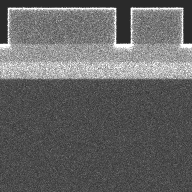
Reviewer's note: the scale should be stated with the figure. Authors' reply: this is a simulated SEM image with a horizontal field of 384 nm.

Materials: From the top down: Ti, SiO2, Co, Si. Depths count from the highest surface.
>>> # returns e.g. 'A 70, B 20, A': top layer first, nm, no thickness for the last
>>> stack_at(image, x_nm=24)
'Ti 72, SiO2 36, Co 34, Si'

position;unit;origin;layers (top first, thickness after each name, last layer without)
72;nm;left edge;Ti 72, SiO2 36, Co 34, Si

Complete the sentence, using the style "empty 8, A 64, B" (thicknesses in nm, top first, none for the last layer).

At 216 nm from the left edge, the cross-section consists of Ti 72, SiO2 36, Co 34, Si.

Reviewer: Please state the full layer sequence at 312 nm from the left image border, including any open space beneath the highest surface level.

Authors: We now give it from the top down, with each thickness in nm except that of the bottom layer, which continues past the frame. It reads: Ti 72, SiO2 36, Co 34, Si